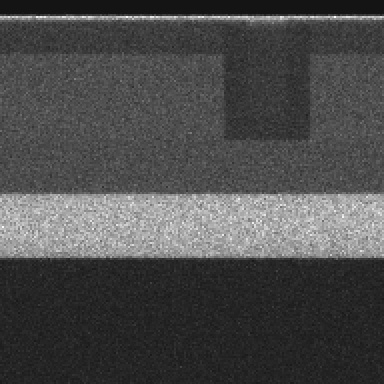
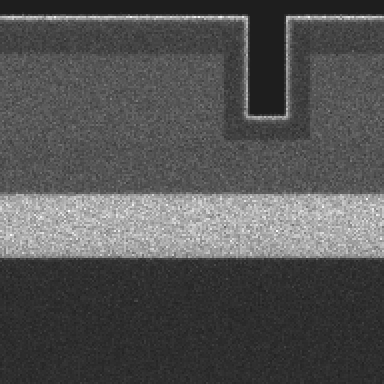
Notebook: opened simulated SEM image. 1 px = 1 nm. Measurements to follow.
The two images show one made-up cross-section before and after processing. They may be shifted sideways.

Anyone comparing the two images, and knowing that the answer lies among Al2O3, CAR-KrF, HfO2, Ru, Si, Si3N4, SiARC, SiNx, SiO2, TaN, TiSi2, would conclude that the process removed SiARC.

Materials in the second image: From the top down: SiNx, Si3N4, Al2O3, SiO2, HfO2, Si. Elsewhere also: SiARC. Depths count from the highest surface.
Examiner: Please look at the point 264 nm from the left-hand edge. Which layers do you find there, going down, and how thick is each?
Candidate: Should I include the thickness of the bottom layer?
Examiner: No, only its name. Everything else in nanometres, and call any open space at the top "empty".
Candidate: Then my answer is empty 100, SiNx 24, SiO2 54, HfO2 64, Si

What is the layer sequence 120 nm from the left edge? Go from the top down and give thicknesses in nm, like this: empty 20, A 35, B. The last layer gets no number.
SiNx 10, Si3N4 28, Al2O3 86, SiO2 54, HfO2 64, Si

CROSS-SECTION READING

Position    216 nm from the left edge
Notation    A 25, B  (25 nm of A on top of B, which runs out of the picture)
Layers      SiNx 10, Si3N4 28, Al2O3 86, SiO2 54, HfO2 64, Si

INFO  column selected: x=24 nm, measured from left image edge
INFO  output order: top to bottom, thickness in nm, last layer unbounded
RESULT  SiNx 10, Si3N4 28, Al2O3 86, SiO2 54, HfO2 64, Si